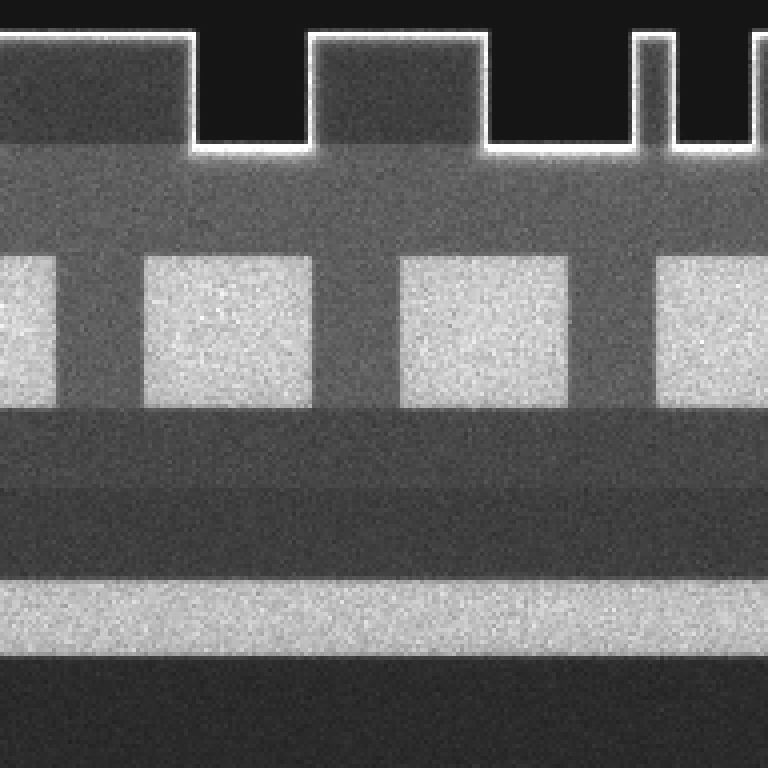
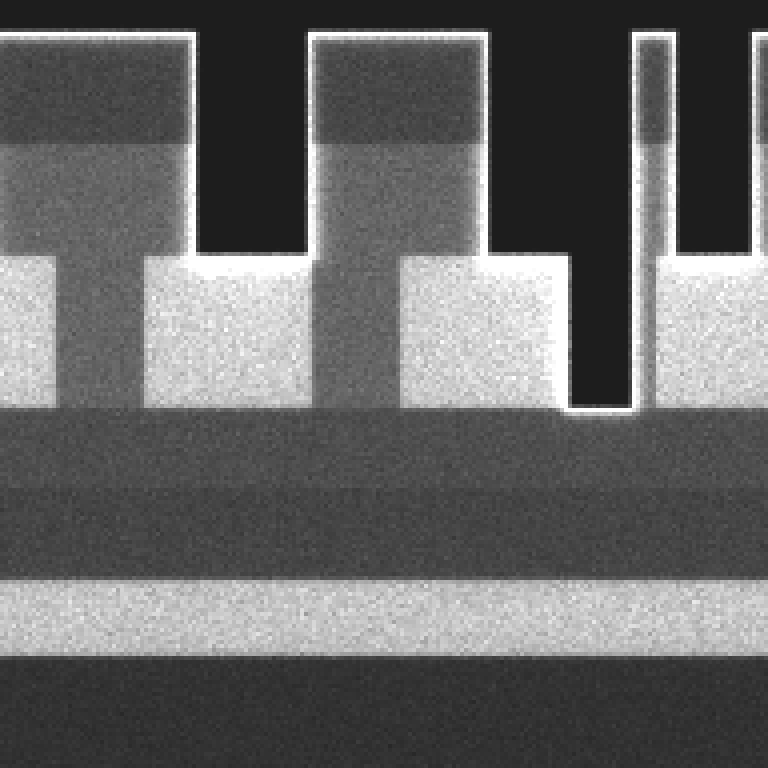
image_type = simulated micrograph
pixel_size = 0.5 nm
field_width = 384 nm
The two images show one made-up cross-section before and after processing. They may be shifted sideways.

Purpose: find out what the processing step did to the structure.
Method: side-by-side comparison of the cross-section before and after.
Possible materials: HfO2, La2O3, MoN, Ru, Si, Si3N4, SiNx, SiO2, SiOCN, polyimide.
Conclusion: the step removed SiO2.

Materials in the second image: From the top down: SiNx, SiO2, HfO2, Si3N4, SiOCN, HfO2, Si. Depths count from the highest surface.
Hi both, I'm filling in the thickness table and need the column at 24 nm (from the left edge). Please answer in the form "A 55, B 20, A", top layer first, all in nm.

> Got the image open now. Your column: SiNx 56, SiO2 56, HfO2 76, Si3N4 40, SiOCN 46, HfO2 38, Si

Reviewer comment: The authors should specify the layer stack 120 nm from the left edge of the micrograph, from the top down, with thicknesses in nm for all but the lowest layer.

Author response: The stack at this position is empty 112, HfO2 76, Si3N4 40, SiOCN 46, HfO2 38, Si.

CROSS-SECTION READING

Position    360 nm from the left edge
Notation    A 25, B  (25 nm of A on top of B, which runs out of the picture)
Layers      empty 112, HfO2 76, Si3N4 40, SiOCN 46, HfO2 38, Si